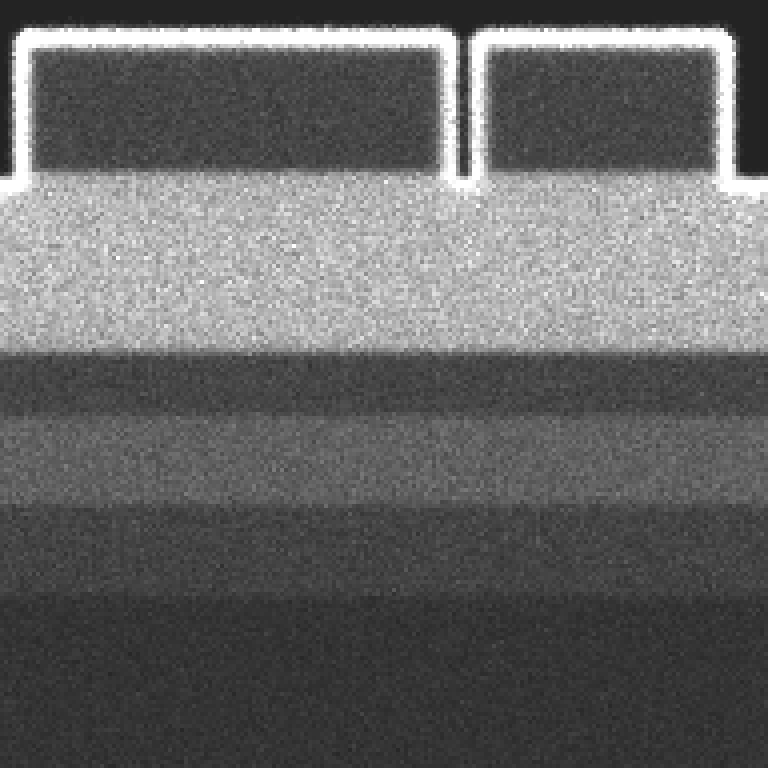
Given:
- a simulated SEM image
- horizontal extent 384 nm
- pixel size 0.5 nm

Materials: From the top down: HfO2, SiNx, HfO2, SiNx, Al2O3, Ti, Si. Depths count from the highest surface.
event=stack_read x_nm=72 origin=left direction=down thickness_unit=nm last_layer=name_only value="HfO2 8, SiNx 62, HfO2 90, SiNx 32, Al2O3 44, Ti 46, Si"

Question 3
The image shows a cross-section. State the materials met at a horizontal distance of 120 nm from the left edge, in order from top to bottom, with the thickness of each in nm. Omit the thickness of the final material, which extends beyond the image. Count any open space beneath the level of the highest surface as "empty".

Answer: HfO2 8, SiNx 62, HfO2 90, SiNx 32, Al2O3 44, Ti 46, Si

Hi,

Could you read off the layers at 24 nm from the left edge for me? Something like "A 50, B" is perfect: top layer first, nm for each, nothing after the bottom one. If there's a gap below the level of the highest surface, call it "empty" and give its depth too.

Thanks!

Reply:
HfO2 8, SiNx 62, HfO2 90, SiNx 32, Al2O3 44, Ti 46, Si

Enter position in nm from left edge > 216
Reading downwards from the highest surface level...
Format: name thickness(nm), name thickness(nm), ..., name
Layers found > HfO2 8, SiNx 62, HfO2 90, SiNx 32, Al2O3 44, Ti 46, Si